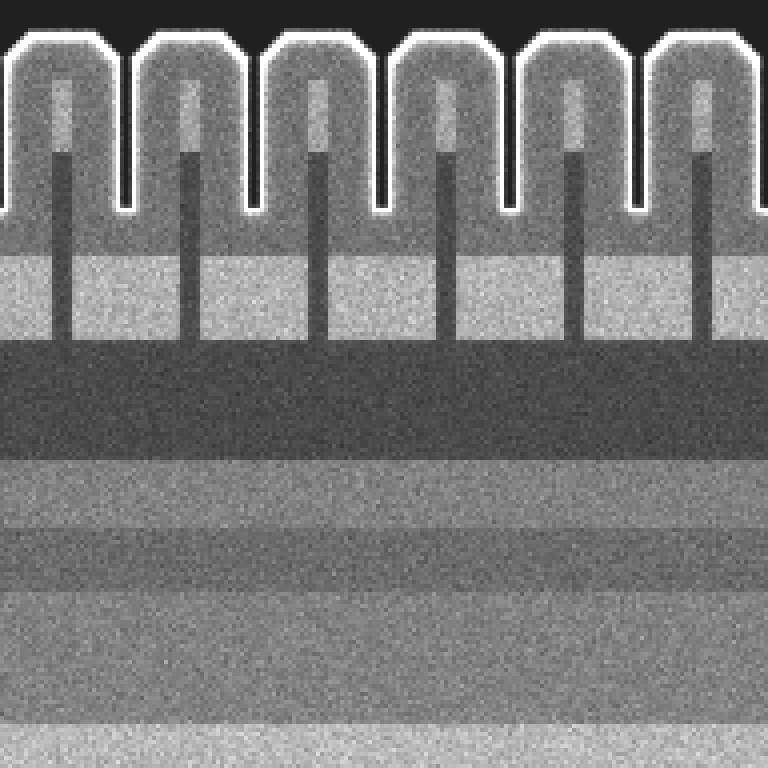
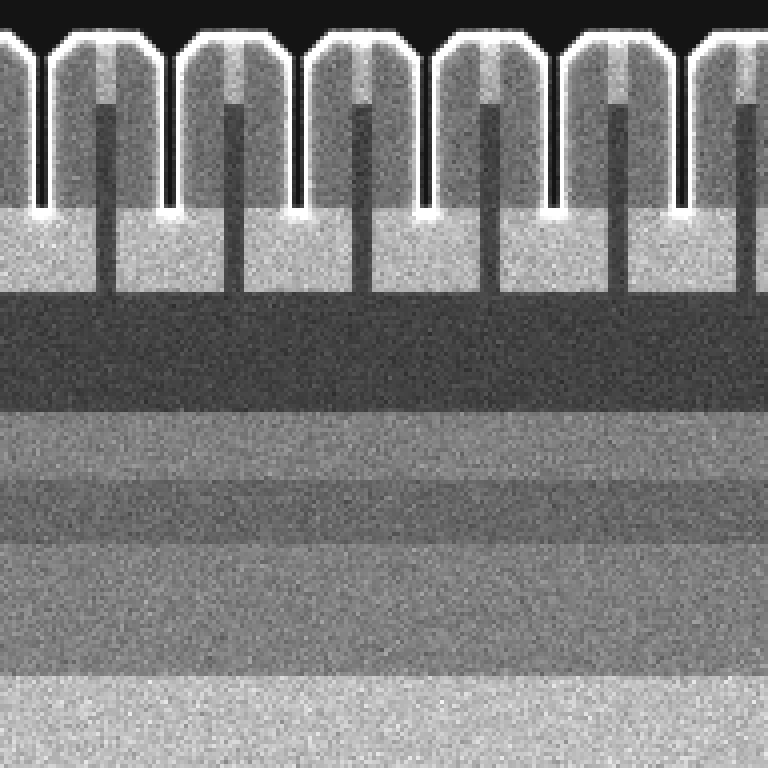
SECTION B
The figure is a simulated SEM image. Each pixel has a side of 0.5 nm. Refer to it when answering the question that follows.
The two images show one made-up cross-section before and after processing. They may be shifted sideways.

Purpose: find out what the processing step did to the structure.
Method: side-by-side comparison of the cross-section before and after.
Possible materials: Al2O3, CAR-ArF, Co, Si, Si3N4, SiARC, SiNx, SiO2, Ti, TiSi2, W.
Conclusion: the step removed SiNx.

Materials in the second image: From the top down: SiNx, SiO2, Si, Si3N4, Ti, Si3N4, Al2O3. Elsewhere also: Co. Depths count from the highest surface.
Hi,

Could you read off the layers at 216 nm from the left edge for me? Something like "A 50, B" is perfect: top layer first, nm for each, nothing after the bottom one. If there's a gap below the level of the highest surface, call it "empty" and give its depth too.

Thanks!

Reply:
empty 12, SiNx 76, SiO2 42, Si 60, Si3N4 34, Ti 32, Si3N4 66, Al2O3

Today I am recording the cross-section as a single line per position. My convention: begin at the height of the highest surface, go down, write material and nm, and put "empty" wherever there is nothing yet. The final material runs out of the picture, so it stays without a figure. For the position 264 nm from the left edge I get empty 4, SiNx 84, SiO2 42, Si 60, Si3N4 34, Ti 32, Si3N4 66, Al2O3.